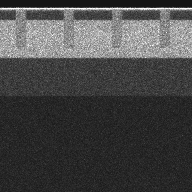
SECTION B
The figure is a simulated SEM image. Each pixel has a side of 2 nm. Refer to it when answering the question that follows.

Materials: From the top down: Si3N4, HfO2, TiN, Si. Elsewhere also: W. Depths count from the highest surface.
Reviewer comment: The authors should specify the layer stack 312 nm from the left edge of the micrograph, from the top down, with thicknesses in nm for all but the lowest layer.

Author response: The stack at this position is Si3N4 24, HfO2 76, TiN 76, Si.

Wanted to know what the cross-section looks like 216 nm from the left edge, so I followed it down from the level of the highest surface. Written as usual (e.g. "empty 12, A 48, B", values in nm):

Si3N4 24, HfO2 76, TiN 76, Si